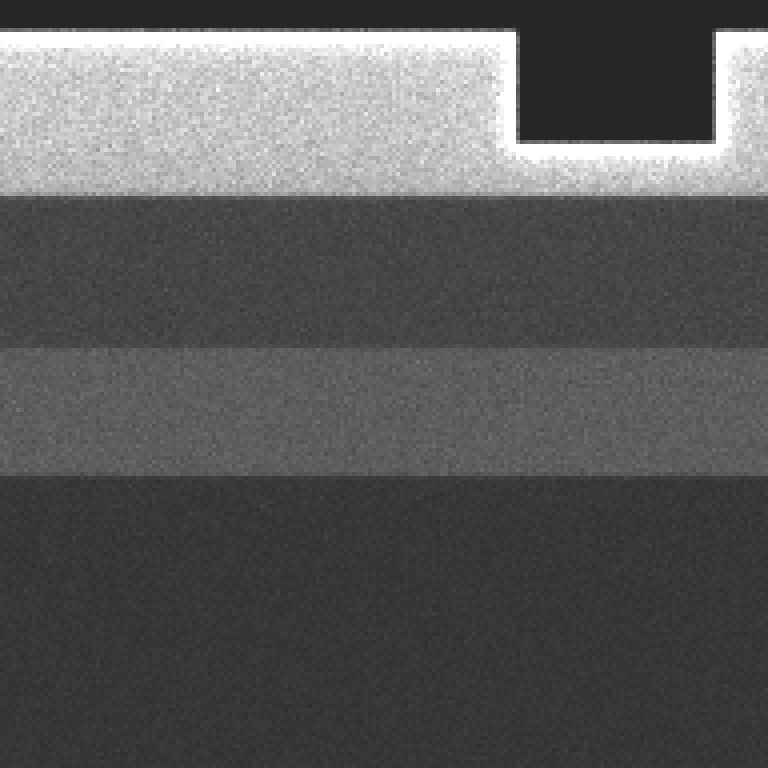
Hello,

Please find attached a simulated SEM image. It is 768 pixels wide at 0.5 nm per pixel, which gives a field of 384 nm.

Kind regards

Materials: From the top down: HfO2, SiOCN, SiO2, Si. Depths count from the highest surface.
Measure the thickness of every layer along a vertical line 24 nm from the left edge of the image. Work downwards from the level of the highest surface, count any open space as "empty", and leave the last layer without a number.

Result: HfO2 82, SiOCN 76, SiO2 64, Si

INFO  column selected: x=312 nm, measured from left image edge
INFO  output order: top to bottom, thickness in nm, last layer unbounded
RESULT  empty 56, HfO2 26, SiOCN 76, SiO2 64, Si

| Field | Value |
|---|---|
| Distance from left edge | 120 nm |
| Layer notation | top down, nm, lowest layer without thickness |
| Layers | HfO2 82, SiOCN 76, SiO2 64, Si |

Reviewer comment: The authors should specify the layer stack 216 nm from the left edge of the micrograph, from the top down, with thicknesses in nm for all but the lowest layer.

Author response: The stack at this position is HfO2 82, SiOCN 76, SiO2 64, Si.